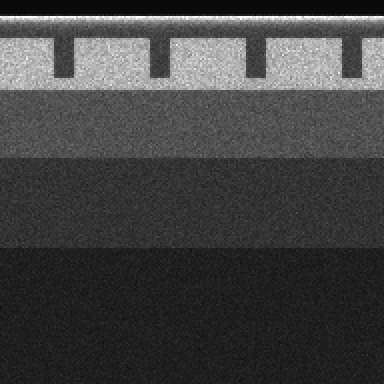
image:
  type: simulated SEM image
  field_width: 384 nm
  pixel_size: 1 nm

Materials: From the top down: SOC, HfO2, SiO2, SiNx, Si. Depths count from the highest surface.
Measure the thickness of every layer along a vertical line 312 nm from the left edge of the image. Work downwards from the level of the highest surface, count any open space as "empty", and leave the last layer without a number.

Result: SOC 22, HfO2 52, SiO2 68, SiNx 90, Si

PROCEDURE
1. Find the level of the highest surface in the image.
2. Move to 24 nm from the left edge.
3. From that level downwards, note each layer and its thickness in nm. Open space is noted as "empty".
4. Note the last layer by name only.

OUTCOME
SOC 22, HfO2 52, SiO2 68, SiNx 90, Si